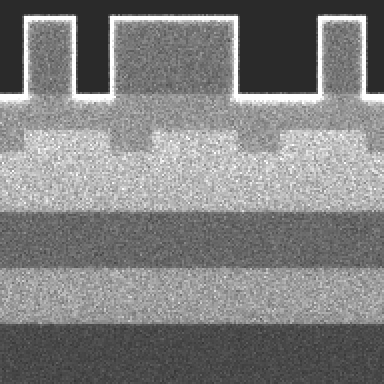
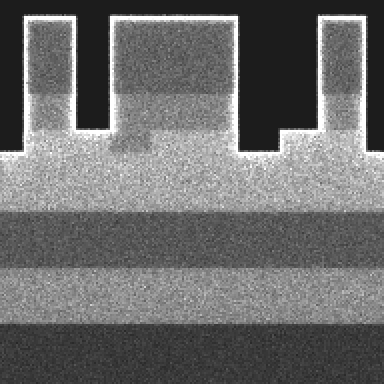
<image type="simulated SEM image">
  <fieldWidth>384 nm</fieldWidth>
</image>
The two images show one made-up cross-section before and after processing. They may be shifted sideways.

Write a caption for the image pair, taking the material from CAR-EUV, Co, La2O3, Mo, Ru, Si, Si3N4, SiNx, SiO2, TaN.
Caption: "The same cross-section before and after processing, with SiO2 removed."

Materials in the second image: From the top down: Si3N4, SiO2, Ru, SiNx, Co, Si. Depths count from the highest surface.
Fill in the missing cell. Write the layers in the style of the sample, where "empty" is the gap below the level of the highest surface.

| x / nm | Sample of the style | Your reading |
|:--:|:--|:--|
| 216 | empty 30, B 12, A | Si3N4 78, SiO2 36, Ru 82, SiNx 56, Co 56, Si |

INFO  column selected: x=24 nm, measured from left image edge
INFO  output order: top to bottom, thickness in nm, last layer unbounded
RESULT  Si3N4 78, SiO2 36, Ru 82, SiNx 56, Co 56, Si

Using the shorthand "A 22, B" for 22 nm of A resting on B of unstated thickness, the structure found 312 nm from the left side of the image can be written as empty 114, Ru 82, SiNx 56, Co 56, Si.